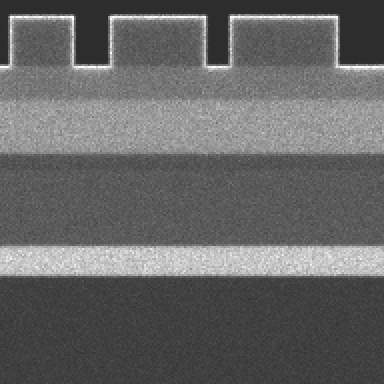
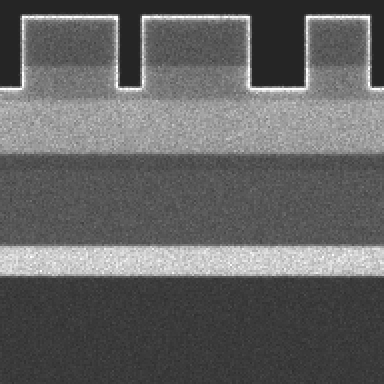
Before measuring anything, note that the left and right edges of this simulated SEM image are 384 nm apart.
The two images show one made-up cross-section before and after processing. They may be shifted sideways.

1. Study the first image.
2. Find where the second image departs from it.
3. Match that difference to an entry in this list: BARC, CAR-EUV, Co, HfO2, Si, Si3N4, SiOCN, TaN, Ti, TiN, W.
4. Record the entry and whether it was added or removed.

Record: Co / removed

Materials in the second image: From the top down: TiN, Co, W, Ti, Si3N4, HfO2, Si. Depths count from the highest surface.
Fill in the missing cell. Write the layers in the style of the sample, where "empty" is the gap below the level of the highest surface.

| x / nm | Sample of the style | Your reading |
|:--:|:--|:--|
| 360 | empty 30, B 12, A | TiN 50, Co 34, W 54, Ti 16, Si3N4 76, HfO2 30, Si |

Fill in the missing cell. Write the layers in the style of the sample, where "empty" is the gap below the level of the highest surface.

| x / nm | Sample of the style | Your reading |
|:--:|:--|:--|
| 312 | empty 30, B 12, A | TiN 50, Co 34, W 54, Ti 16, Si3N4 76, HfO2 30, Si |